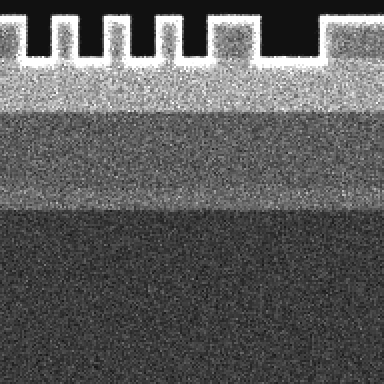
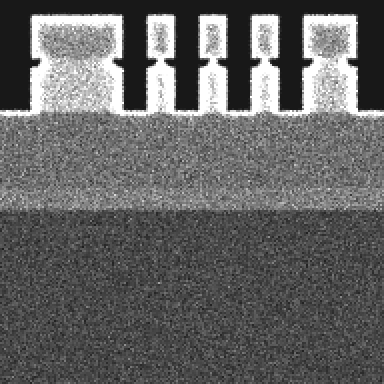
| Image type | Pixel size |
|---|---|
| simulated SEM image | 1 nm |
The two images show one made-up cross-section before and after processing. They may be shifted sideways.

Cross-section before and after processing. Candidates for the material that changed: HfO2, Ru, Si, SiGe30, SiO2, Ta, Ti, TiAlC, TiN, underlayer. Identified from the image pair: SiO2 (removed).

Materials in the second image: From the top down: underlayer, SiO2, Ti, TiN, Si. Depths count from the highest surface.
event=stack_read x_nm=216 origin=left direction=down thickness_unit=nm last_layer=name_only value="underlayer 42, empty 6, SiO2 48, Ti 76, TiN 22, Si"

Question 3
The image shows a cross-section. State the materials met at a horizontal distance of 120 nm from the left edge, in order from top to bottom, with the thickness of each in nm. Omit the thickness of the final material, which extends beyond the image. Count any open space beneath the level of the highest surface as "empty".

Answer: underlayer 42, empty 10, SiO2 44, Ti 76, TiN 22, Si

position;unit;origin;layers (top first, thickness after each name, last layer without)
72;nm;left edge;underlayer 42, SiO2 54, Ti 76, TiN 22, Si